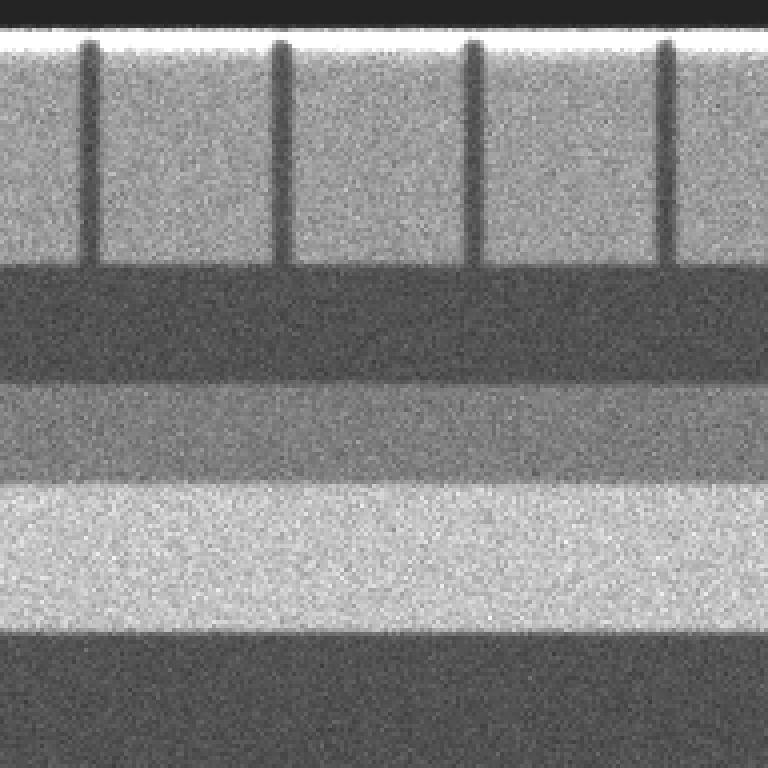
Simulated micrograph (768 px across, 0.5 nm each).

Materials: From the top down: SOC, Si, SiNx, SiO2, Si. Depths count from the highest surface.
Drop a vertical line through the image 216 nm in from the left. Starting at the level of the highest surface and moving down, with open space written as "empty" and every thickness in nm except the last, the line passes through SOC 116, Si 60, SiNx 50, SiO2 74, Si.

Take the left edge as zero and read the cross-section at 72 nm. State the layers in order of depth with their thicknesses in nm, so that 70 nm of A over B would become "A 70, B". SOC 116, Si 60, SiNx 50, SiO2 74, Si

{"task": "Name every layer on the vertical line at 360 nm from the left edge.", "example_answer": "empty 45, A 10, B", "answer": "SOC 116, Si 60, SiNx 50, SiO2 74, Si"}